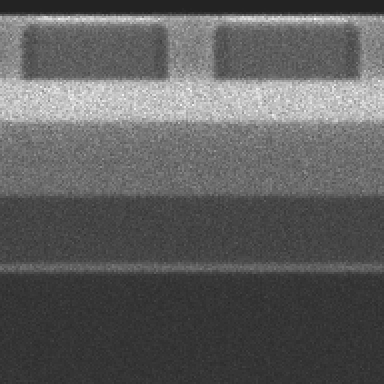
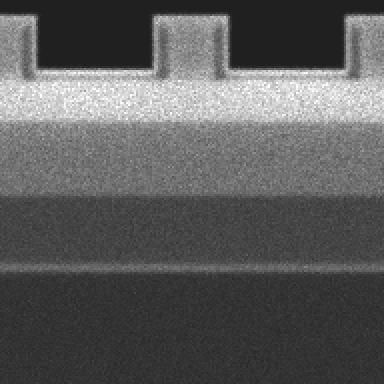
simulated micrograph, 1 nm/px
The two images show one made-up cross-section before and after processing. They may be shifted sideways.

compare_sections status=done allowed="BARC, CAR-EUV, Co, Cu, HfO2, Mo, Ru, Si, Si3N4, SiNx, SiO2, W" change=removed material="SiO2"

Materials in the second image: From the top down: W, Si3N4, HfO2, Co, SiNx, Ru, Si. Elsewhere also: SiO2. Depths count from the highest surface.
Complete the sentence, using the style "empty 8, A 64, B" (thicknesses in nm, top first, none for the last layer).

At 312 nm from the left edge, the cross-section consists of empty 54, SiO2 10, HfO2 42, Co 74, SiNx 68, Ru 8, Si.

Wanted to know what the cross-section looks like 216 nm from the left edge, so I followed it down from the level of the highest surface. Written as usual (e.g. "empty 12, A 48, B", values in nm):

W 12, Si3N4 52, HfO2 42, Co 74, SiNx 68, Ru 8, Si